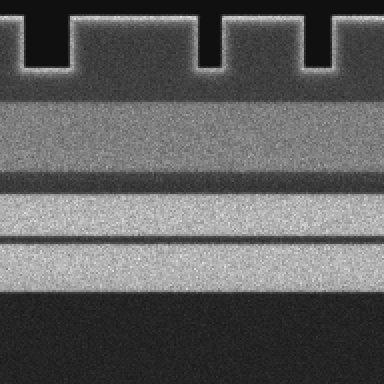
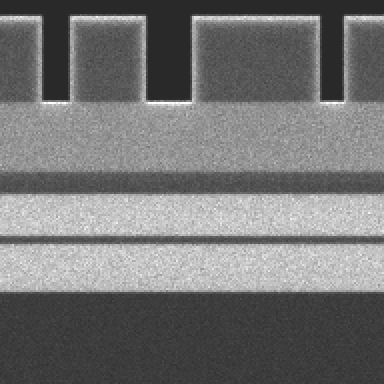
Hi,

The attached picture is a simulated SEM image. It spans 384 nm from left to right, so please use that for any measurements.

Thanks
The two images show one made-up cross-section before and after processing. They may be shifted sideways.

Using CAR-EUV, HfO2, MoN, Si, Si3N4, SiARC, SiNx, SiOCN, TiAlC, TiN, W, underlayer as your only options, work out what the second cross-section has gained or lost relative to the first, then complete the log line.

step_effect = removed underlayer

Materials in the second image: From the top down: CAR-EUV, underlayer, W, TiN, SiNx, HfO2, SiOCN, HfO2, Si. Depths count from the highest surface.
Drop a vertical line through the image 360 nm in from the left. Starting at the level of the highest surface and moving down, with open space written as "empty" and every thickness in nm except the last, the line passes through CAR-EUV 52, underlayer 34, W 70, TiN 10, SiNx 12, HfO2 42, SiOCN 8, HfO2 48, Si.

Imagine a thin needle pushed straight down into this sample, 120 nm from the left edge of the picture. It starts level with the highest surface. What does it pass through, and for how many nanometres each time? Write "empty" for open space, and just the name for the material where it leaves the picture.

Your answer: CAR-EUV 52, underlayer 34, W 70, TiN 10, SiNx 12, HfO2 42, SiOCN 8, HfO2 48, Si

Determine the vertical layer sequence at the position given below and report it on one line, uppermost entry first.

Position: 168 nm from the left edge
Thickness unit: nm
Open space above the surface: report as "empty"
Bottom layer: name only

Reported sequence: empty 86, W 70, TiN 10, SiNx 12, HfO2 42, SiOCN 8, HfO2 48, Si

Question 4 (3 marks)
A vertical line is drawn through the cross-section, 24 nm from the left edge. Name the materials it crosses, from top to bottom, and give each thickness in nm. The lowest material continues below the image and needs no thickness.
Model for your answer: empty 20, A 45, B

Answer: CAR-EUV 52, underlayer 34, W 70, TiN 10, SiNx 12, HfO2 42, SiOCN 8, HfO2 48, Si